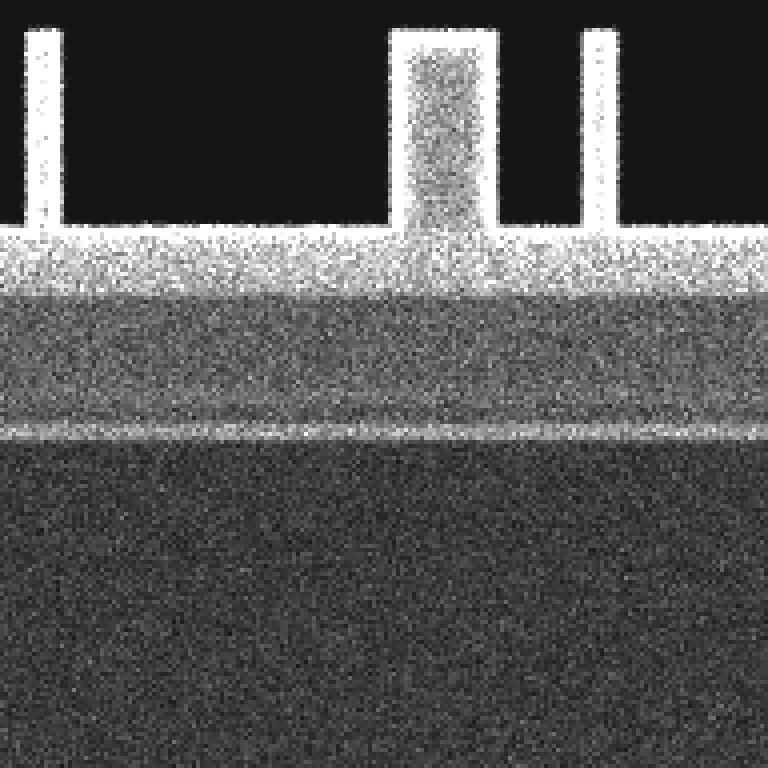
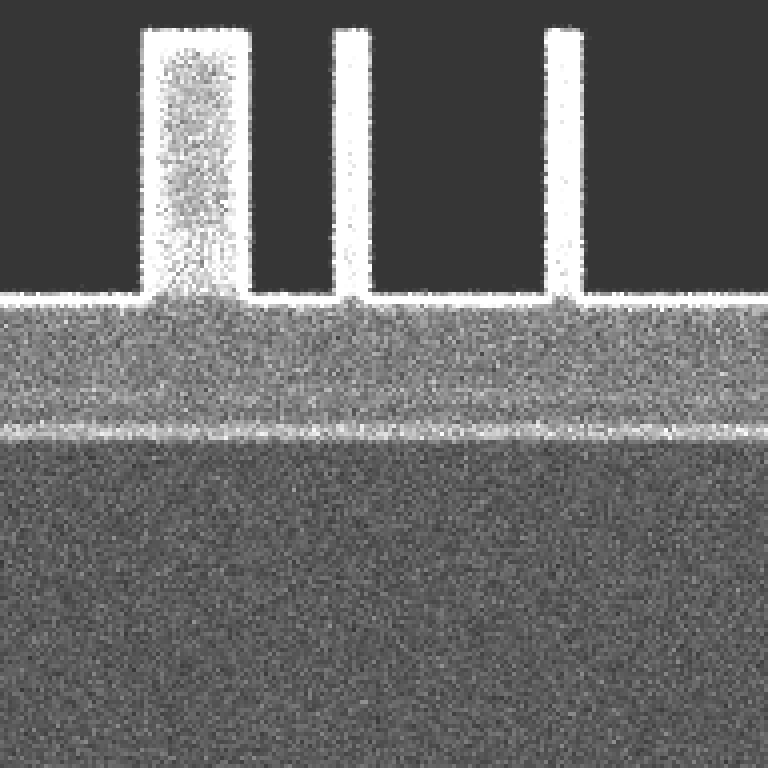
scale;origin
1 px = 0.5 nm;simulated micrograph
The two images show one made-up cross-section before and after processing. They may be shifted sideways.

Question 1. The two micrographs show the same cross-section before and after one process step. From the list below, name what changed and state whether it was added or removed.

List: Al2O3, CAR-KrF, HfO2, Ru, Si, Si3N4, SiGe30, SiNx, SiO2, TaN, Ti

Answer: Ru, removed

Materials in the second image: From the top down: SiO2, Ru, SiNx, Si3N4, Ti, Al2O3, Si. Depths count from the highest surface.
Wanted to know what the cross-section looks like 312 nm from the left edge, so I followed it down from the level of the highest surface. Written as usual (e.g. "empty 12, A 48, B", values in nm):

empty 132, SiNx 46, Si3N4 8, Ti 10, Al2O3 8, Si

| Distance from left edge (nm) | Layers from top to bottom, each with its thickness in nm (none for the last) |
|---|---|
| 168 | SiO2 98, Ru 34, SiNx 46, Si3N4 8, Ti 10, Al2O3 8, Si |